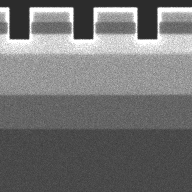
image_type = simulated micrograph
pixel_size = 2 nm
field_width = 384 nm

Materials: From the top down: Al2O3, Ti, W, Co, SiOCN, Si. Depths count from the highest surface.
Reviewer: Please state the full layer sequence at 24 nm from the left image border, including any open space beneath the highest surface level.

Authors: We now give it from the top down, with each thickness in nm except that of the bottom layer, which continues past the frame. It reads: empty 64, W 28, Co 82, SiOCN 68, Si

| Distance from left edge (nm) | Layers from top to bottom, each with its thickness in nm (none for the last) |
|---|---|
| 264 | Al2O3 28, Ti 24, W 40, Co 82, SiOCN 68, Si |